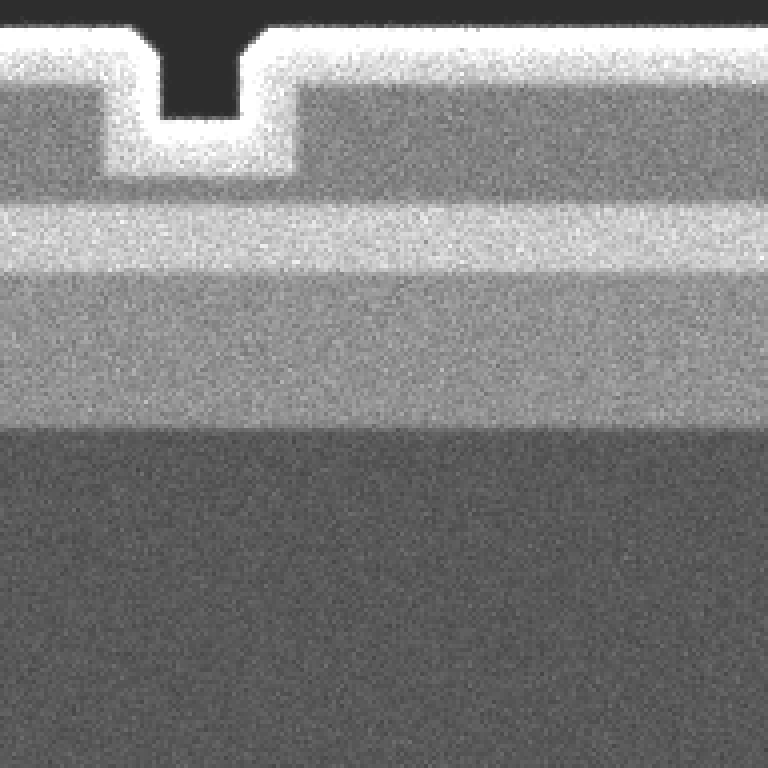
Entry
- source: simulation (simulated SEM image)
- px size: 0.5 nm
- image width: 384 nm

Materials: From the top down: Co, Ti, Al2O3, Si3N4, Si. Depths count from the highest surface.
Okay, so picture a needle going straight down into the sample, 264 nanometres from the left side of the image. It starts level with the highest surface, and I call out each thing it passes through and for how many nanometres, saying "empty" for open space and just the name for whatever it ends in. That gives Co 26, Ti 60, Al2O3 34, Si3N4 78, Si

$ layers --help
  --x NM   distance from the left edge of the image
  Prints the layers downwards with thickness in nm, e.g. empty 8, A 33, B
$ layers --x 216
Co 26, Ti 60, Al2O3 34, Si3N4 78, Si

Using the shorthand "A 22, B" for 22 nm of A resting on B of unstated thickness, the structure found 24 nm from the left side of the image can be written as Co 26, Ti 60, Al2O3 34, Si3N4 78, Si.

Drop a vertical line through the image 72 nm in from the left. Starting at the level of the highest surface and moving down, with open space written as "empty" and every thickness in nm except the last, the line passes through empty 8, Co 64, Ti 14, Al2O3 34, Si3N4 78, Si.